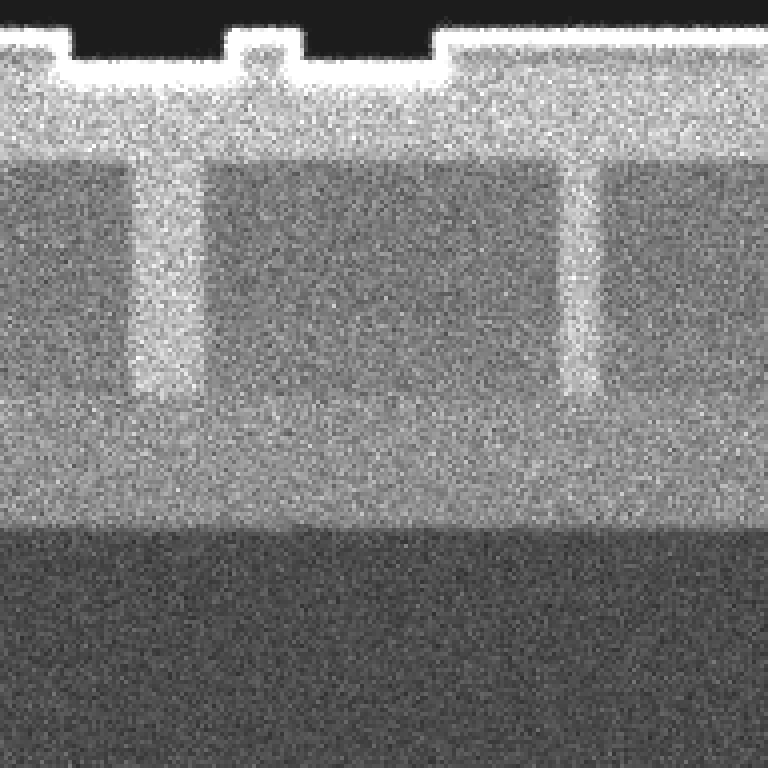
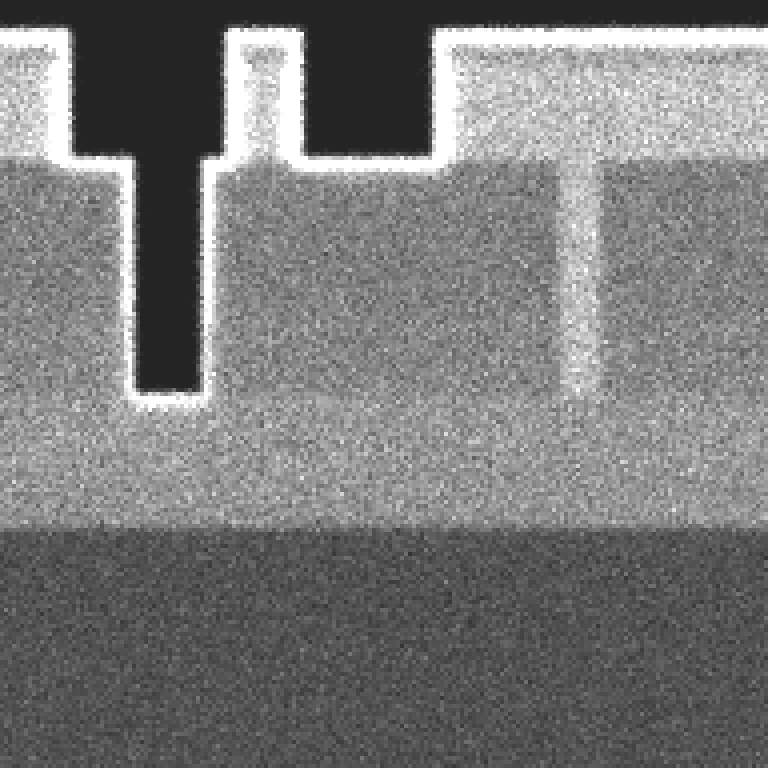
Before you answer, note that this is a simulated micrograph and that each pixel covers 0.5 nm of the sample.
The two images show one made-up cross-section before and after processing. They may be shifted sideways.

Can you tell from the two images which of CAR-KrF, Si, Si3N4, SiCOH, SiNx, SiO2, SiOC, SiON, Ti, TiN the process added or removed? Yes, it removed SiO2.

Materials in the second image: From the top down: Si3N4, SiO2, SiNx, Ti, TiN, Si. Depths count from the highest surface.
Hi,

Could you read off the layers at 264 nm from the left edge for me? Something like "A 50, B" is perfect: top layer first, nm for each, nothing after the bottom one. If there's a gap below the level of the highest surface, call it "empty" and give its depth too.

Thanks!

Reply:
Si3N4 16, SiO2 48, SiNx 78, Ti 40, TiN 66, Si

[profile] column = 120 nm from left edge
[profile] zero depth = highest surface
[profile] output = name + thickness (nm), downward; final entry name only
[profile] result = Si3N4 16, SiO2 48, SiNx 78, Ti 40, TiN 66, Si